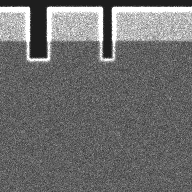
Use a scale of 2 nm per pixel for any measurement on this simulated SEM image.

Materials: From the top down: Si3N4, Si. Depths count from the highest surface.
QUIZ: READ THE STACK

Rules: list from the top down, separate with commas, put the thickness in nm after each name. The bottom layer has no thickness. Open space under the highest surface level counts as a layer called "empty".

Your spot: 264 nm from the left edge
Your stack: Si3N4 66, Si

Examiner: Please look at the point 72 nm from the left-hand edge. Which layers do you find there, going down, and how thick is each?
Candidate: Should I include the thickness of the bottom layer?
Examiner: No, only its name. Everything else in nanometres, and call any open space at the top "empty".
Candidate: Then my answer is empty 102, Si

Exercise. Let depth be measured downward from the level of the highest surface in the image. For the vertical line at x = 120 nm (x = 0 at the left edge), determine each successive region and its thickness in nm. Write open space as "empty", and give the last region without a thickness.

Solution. Si3N4 66, Si